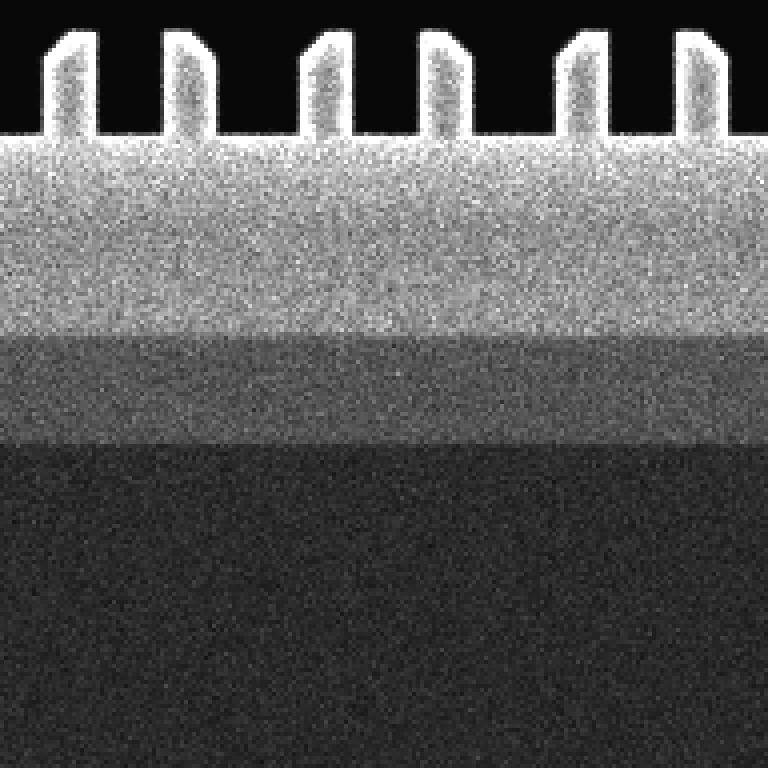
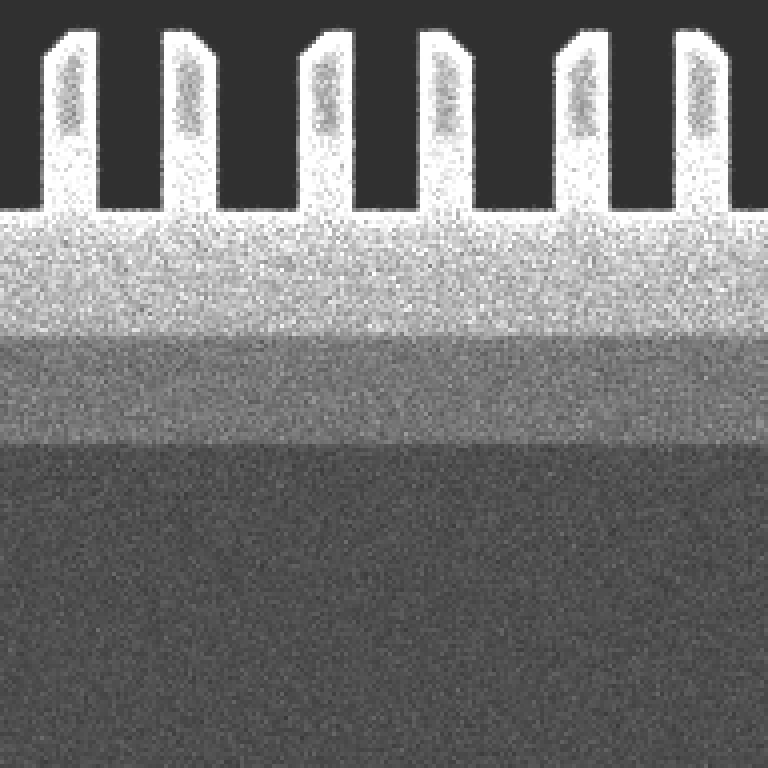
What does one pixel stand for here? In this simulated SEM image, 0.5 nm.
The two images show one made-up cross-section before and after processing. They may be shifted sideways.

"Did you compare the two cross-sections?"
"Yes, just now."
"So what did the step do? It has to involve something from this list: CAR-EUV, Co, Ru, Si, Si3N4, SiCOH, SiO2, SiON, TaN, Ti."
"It removed Ru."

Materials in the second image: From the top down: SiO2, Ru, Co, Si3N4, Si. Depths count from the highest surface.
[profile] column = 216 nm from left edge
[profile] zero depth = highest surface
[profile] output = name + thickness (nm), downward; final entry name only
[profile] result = SiO2 52, Ru 38, Co 62, Si3N4 54, Si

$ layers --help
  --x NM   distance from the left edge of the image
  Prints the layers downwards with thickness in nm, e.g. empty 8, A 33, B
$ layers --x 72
empty 90, Co 62, Si3N4 54, Si